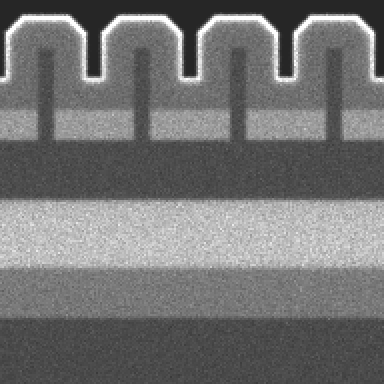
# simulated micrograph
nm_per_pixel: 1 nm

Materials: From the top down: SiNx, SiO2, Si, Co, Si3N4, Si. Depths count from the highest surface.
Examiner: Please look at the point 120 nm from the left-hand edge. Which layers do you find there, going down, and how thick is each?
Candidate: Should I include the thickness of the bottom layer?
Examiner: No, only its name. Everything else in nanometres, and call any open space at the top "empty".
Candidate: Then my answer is SiNx 94, SiO2 30, Si 60, Co 68, Si3N4 50, Si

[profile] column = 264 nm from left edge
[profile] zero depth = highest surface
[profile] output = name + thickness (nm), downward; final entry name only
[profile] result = empty 4, SiNx 90, SiO2 30, Si 60, Co 68, Si3N4 50, Si